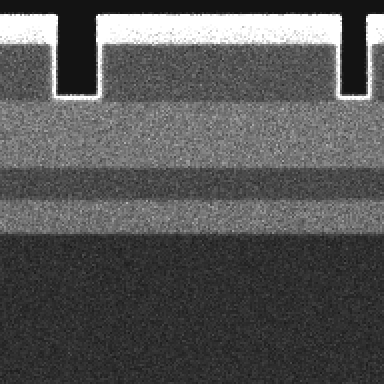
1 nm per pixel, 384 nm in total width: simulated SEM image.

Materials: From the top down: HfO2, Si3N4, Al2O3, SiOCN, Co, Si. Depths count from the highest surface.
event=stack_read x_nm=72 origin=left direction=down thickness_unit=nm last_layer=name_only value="empty 80, Si3N4 6, Al2O3 66, SiOCN 32, Co 34, Si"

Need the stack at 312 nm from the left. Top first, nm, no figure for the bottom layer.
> HfO2 28, Si3N4 58, Al2O3 66, SiOCN 32, Co 34, Si